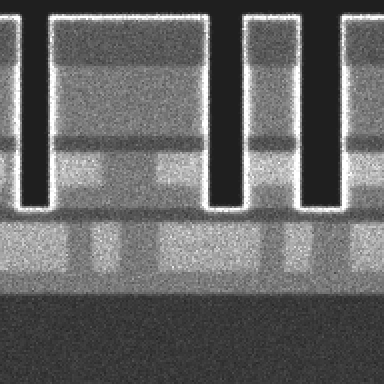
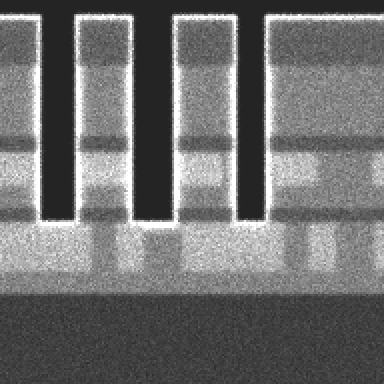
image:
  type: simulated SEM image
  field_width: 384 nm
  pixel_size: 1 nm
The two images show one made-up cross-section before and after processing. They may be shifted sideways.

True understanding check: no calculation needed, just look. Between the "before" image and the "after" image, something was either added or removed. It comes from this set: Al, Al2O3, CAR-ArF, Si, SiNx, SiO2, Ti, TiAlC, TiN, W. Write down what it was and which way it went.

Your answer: SiNx (removed)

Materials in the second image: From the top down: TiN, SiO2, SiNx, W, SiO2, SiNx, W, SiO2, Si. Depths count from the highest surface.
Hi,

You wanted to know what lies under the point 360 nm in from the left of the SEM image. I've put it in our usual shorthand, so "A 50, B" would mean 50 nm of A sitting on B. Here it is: TiN 50, SiO2 70, SiNx 16, SiO2 56, SiNx 14, SiO2 72, Si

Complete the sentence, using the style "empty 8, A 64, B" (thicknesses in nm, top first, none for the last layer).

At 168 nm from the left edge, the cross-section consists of empty 206, SiO2 72, Si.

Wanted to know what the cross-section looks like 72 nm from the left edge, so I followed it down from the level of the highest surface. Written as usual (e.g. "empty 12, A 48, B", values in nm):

empty 206, W 50, SiO2 22, Si